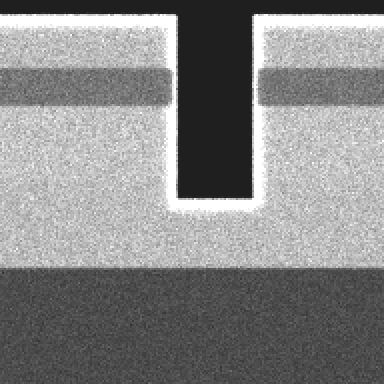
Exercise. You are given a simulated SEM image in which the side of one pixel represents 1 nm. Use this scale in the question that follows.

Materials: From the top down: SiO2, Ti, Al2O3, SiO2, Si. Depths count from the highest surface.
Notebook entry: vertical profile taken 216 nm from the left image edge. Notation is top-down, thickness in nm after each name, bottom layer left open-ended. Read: empty 184, SiO2 68, Si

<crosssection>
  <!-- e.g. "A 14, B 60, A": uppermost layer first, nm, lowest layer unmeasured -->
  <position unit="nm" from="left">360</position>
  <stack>SiO2 52, Ti 38, Al2O3 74, SiO2 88, Si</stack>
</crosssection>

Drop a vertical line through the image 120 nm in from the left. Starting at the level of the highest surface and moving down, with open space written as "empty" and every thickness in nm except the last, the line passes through SiO2 52, Ti 38, Al2O3 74, SiO2 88, Si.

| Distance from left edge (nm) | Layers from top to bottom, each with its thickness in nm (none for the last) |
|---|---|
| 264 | SiO2 52, Ti 38, Al2O3 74, SiO2 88, Si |